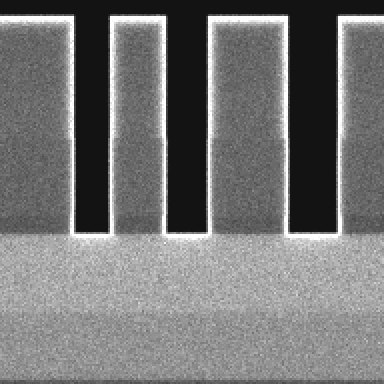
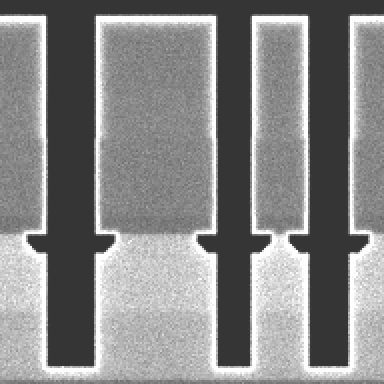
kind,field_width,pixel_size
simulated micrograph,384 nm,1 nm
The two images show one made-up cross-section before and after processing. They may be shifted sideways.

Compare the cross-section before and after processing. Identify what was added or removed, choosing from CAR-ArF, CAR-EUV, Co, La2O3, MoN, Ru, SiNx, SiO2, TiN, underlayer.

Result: Co and Ru removed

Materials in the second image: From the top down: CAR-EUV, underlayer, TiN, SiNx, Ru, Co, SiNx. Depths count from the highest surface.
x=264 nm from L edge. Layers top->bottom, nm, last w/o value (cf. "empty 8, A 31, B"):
CAR-EUV 74, underlayer 48, TiN 78, SiNx 18, empty 16, Ru 62, Co 68, SiNx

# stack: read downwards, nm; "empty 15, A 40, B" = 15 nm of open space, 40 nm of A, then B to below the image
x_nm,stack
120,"CAR-EUV 74, underlayer 48, TiN 78, SiNx 18, Ru 78, Co 68, SiNx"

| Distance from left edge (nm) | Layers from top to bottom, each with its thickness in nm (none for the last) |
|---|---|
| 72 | empty 352, Co 12, SiNx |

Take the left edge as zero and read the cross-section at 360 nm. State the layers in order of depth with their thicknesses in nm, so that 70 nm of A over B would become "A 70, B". CAR-EUV 74, underlayer 48, TiN 78, SiNx 18, empty 18, Ru 60, Co 68, SiNx